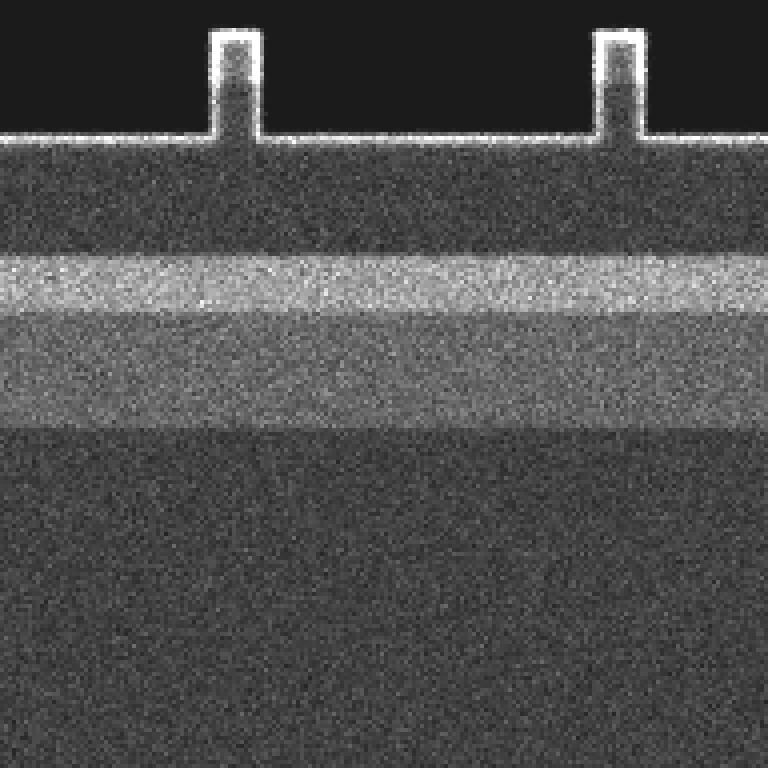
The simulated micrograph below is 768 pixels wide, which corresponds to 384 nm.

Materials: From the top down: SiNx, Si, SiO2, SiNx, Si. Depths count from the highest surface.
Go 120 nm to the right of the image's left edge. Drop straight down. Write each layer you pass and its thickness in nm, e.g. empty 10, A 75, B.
SiNx 26, Si 86, SiO2 28, SiNx 58, Si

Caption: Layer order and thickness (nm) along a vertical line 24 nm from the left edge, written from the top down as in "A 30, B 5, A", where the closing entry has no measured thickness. empty 52, Si 60, SiO2 28, SiNx 58, Si